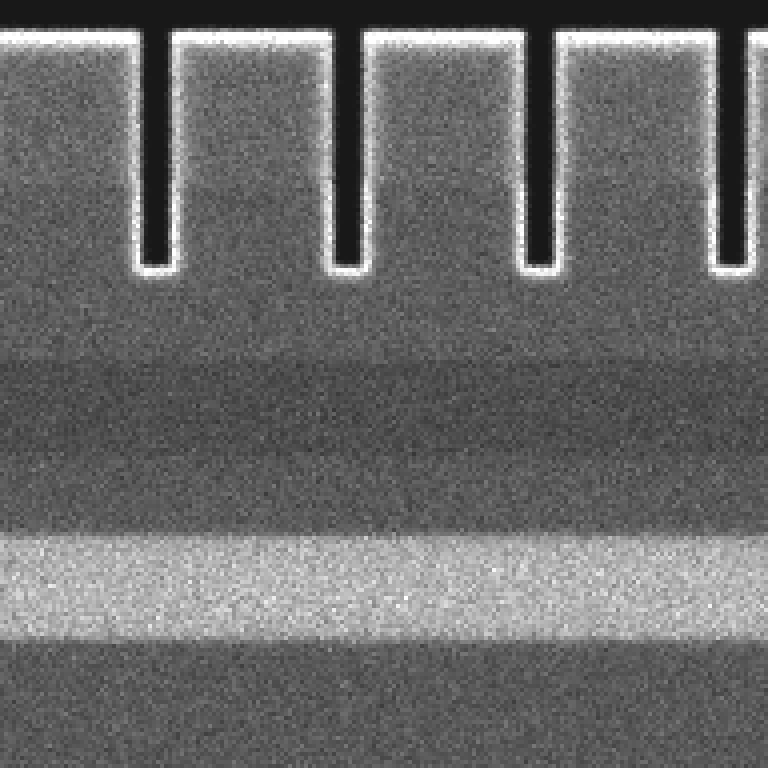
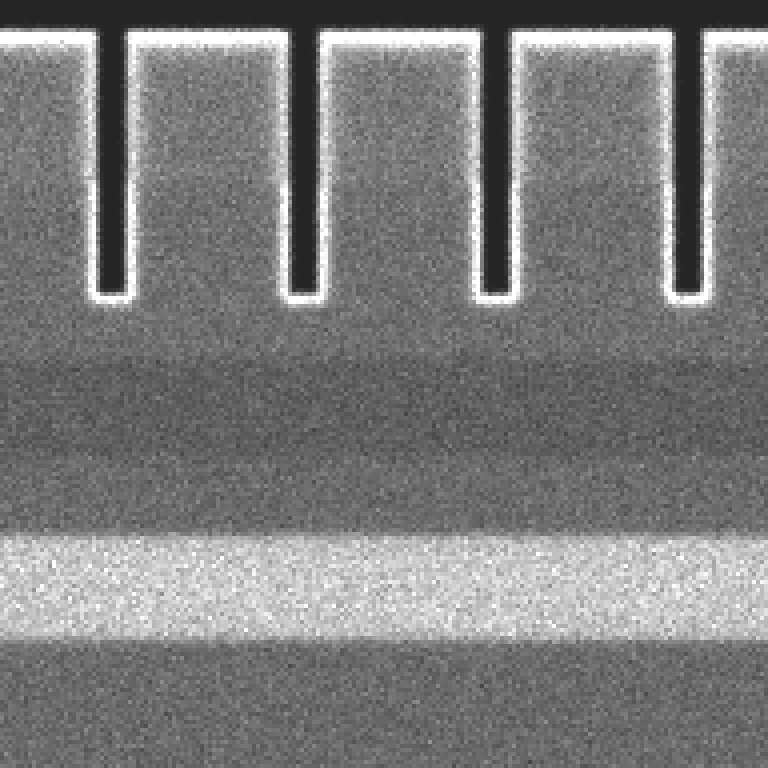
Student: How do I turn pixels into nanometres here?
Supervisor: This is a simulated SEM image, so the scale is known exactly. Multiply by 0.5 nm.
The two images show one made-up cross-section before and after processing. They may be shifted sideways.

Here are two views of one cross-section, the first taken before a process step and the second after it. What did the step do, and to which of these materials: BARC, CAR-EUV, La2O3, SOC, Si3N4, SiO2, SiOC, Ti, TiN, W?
It removed Si3N4.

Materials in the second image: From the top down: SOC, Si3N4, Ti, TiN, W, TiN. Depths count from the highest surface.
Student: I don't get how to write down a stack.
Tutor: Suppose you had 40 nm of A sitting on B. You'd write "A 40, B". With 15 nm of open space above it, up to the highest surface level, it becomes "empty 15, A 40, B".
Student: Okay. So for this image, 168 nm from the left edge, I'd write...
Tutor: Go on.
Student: SOC 76, Si3N4 88, Ti 48, TiN 40, W 52, TiN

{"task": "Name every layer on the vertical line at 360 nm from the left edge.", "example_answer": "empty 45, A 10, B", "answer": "SOC 76, Si3N4 88, Ti 48, TiN 40, W 52, TiN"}